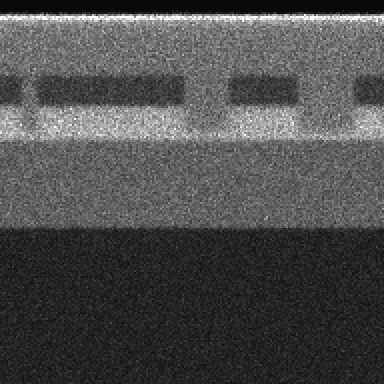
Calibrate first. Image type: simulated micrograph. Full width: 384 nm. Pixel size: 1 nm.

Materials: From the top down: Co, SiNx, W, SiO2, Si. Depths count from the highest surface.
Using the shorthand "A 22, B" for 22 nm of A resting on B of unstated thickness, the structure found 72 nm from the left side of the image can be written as Co 60, SiNx 30, W 34, SiO2 88, Si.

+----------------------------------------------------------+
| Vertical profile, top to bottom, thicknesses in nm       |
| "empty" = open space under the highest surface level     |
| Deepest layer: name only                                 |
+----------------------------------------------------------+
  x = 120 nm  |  Co 60, SiNx 30, W 34, SiO2 88, Si